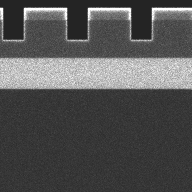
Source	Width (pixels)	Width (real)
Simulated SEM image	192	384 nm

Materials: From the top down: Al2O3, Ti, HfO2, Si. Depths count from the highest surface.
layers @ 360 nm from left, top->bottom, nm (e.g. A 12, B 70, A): Al2O3 24, Ti 76, HfO2 62, Si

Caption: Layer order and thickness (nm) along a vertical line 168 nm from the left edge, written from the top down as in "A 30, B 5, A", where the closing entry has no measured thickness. empty 64, Ti 36, HfO2 62, Si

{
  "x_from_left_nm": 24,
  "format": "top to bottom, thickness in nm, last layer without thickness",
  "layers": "empty 64, Ti 36, HfO2 62, Si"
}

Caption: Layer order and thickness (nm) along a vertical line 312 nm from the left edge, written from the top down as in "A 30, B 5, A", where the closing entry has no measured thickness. Al2O3 24, Ti 76, HfO2 62, Si